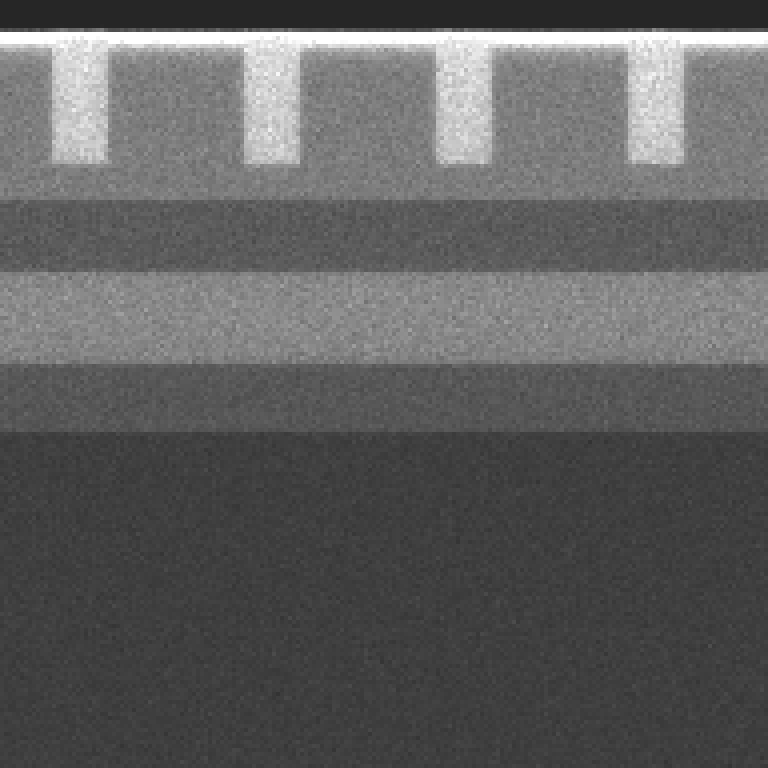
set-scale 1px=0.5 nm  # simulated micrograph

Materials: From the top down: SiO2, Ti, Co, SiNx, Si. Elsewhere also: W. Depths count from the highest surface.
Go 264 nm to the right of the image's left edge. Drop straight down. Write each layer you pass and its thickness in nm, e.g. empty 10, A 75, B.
SiO2 84, Ti 36, Co 46, SiNx 34, Si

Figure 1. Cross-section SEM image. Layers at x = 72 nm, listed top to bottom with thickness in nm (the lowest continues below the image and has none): SiO2 84, Ti 36, Co 46, SiNx 34, Si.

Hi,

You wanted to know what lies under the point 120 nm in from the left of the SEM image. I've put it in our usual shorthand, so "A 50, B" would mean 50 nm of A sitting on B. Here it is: SiO2 84, Ti 36, Co 46, SiNx 34, Si